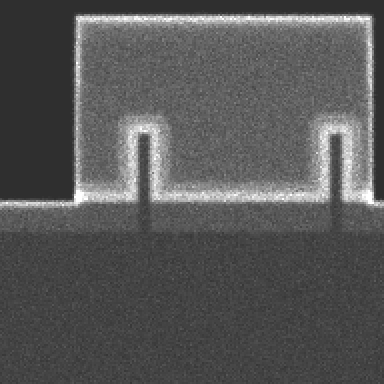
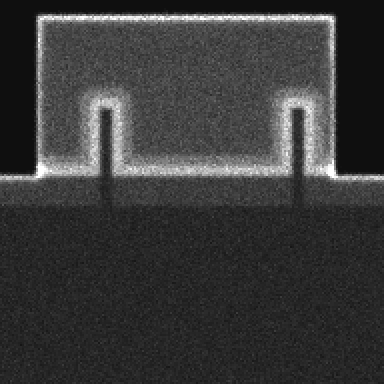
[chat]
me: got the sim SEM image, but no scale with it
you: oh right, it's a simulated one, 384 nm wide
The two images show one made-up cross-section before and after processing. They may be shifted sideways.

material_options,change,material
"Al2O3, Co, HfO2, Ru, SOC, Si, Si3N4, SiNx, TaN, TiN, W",removed,SOC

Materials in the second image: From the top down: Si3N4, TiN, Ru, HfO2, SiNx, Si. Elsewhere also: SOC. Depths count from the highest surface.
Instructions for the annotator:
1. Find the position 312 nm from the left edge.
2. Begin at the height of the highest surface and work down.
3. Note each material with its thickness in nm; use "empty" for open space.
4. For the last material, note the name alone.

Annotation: Si3N4 44, TiN 28, Ru 14, HfO2 74, SiNx 30, Si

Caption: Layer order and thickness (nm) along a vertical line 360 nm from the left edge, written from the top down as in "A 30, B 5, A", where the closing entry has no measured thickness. empty 160, SiNx 30, Si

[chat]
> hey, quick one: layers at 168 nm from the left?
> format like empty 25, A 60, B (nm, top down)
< Si3N4 44, TiN 96, Ru 10, HfO2 10, SiNx 30, Si